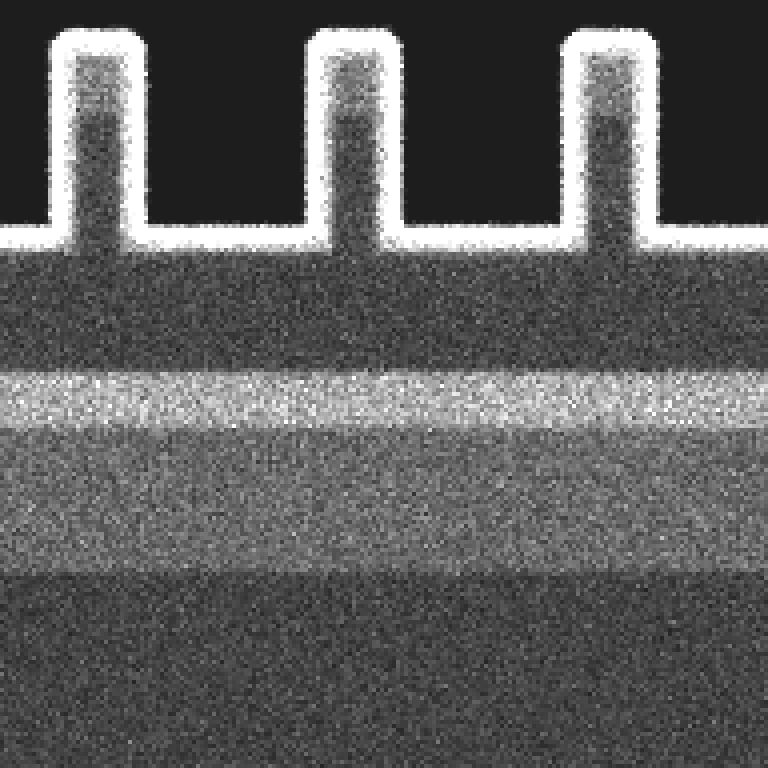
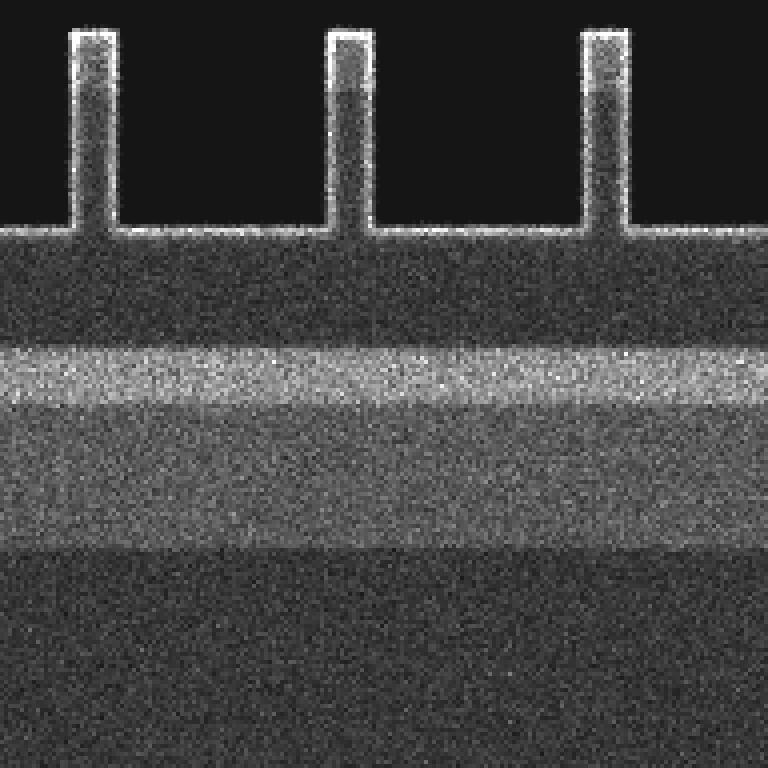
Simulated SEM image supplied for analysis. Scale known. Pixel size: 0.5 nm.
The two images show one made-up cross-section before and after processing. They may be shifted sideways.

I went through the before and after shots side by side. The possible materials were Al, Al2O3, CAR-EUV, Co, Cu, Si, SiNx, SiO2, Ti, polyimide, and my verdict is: removed, Al2O3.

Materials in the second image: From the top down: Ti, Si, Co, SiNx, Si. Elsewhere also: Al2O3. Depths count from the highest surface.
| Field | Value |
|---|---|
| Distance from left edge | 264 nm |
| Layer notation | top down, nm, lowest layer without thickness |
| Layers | empty 98, Si 60, Co 28, SiNx 72, Si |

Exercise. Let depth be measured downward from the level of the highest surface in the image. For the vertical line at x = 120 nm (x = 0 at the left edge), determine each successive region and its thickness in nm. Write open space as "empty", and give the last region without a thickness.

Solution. empty 98, Si 60, Co 28, SiNx 72, Si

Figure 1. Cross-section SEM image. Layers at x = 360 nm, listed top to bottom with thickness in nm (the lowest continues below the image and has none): empty 98, Si 60, Co 28, SiNx 72, Si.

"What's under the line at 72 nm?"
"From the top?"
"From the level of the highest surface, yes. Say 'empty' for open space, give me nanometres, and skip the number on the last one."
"empty 98, Si 60, Co 28, SiNx 72, Si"